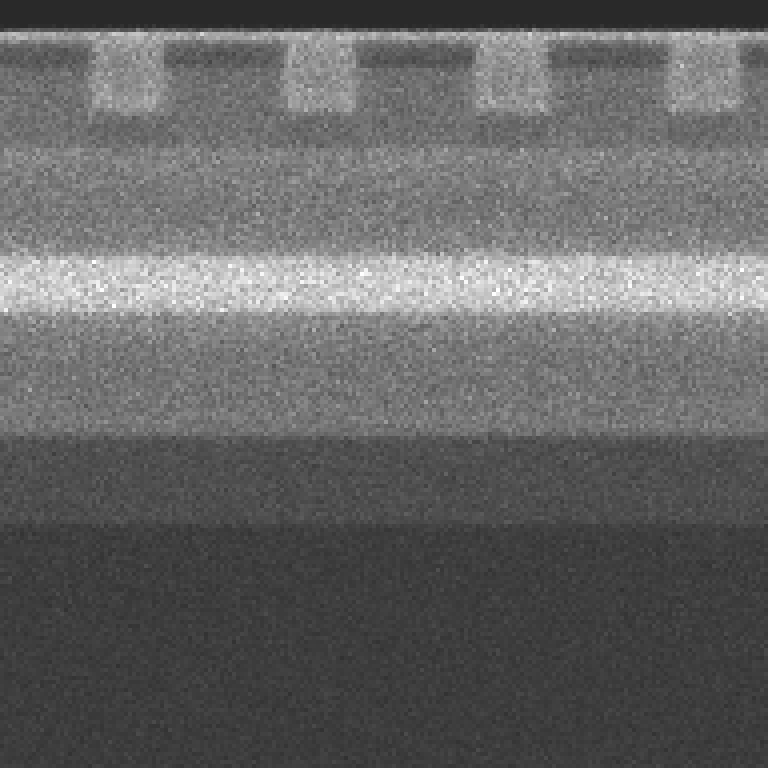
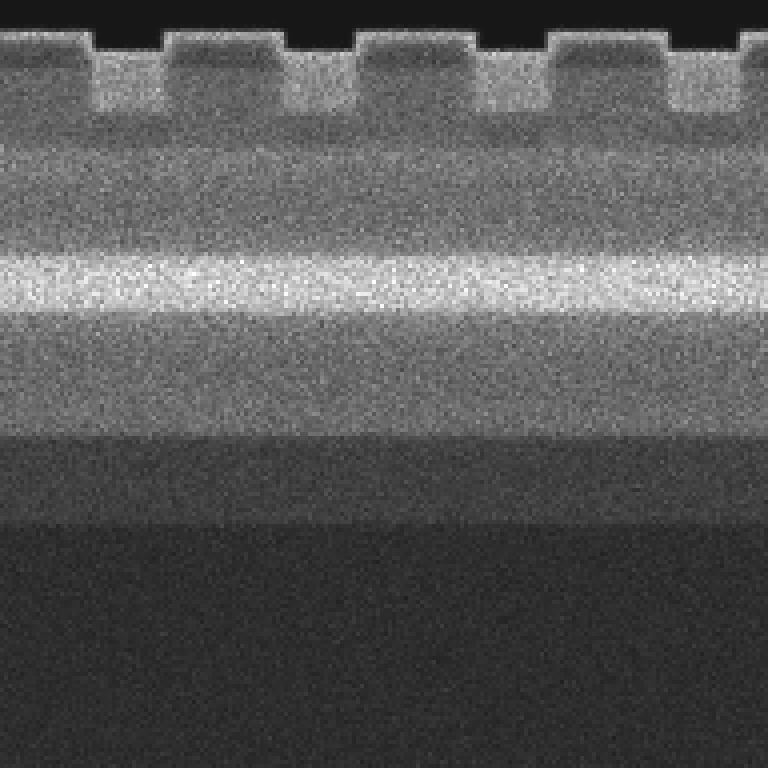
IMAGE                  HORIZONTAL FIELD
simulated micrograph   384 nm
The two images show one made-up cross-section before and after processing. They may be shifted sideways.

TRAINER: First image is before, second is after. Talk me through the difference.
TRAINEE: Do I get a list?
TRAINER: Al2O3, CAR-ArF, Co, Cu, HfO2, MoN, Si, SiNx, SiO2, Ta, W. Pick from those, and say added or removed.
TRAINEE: removed: W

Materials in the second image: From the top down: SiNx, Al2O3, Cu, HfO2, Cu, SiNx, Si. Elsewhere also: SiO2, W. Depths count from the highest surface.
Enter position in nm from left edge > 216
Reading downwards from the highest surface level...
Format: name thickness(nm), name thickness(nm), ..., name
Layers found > SiNx 18, Al2O3 40, Cu 54, HfO2 28, Cu 62, SiNx 44, Si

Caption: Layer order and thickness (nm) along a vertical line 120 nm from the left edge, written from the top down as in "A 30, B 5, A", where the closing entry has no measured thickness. SiNx 18, Al2O3 40, Cu 54, HfO2 28, Cu 62, SiNx 44, Si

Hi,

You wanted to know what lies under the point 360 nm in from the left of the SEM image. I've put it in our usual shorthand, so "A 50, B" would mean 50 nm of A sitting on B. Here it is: empty 10, W 30, SiO2 18, Cu 54, HfO2 28, Cu 62, SiNx 44, Si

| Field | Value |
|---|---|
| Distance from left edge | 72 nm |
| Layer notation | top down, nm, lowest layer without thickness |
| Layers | empty 10, W 30, SiO2 18, Cu 54, HfO2 28, Cu 62, SiNx 44, Si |